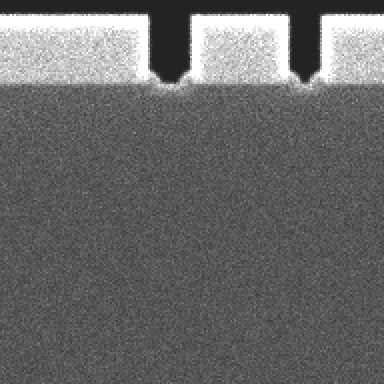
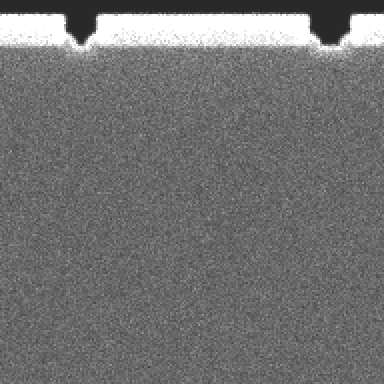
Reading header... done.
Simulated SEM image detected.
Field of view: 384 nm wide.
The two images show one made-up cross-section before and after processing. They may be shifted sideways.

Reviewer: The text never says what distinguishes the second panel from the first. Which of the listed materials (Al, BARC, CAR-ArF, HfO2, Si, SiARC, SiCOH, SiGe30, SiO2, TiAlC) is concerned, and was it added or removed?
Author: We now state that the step removed SiO2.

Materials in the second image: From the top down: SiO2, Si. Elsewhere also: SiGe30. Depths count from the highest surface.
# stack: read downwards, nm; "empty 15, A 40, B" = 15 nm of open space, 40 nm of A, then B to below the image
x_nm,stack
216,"SiO2 30, Si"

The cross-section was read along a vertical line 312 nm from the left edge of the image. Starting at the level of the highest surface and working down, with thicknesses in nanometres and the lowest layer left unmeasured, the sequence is empty 18, SiGe30 24, Si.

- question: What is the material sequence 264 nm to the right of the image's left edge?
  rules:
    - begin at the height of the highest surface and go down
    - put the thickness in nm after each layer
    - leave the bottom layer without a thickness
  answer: SiO2 30, Si